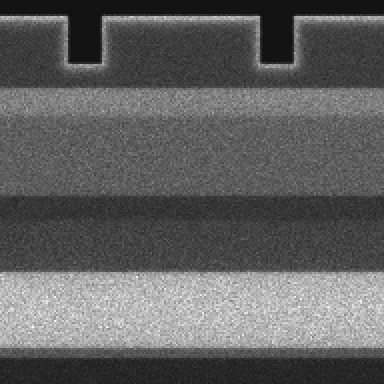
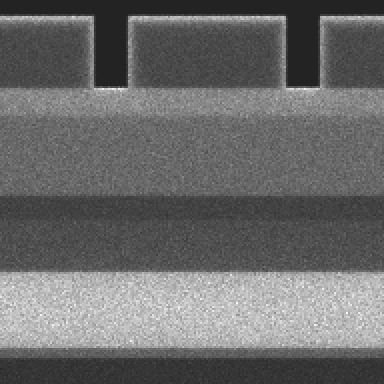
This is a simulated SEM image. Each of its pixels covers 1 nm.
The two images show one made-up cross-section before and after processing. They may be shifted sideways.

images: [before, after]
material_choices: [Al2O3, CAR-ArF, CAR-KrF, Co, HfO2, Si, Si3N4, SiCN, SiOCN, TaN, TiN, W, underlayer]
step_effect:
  removed: underlayer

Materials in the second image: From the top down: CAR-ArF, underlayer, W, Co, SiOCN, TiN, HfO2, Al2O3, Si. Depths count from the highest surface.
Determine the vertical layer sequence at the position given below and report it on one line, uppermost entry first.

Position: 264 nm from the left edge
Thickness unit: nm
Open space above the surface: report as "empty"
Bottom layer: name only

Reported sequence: CAR-ArF 48, underlayer 24, W 28, Co 80, SiOCN 24, TiN 52, HfO2 76, Al2O3 10, Si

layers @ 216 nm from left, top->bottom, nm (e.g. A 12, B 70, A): CAR-ArF 48, underlayer 24, W 28, Co 80, SiOCN 24, TiN 52, HfO2 76, Al2O3 10, Si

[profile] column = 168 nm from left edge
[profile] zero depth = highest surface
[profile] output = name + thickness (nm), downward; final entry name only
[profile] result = CAR-ArF 48, underlayer 24, W 28, Co 80, SiOCN 24, TiN 52, HfO2 76, Al2O3 10, Si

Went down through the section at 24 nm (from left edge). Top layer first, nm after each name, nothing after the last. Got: CAR-ArF 48, underlayer 24, W 28, Co 80, SiOCN 24, TiN 52, HfO2 76, Al2O3 10, Si